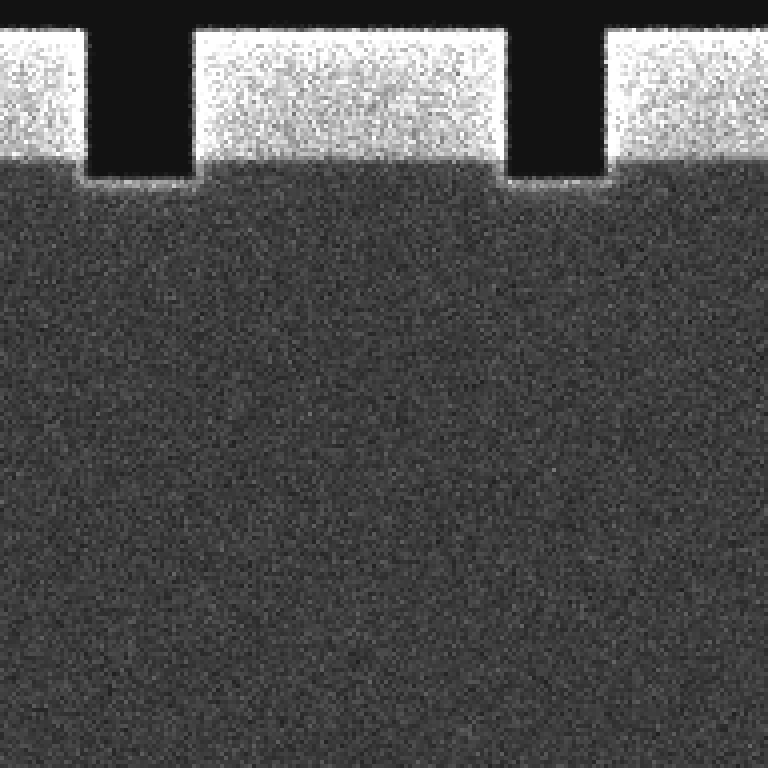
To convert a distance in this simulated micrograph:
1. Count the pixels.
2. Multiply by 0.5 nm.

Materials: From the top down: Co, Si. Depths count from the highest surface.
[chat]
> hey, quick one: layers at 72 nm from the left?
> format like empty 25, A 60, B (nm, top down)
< empty 74, Si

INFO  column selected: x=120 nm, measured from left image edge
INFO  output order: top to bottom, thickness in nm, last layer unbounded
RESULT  Co 64, Si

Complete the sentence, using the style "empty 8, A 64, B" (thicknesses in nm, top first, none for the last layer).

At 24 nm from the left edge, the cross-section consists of Co 64, Si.